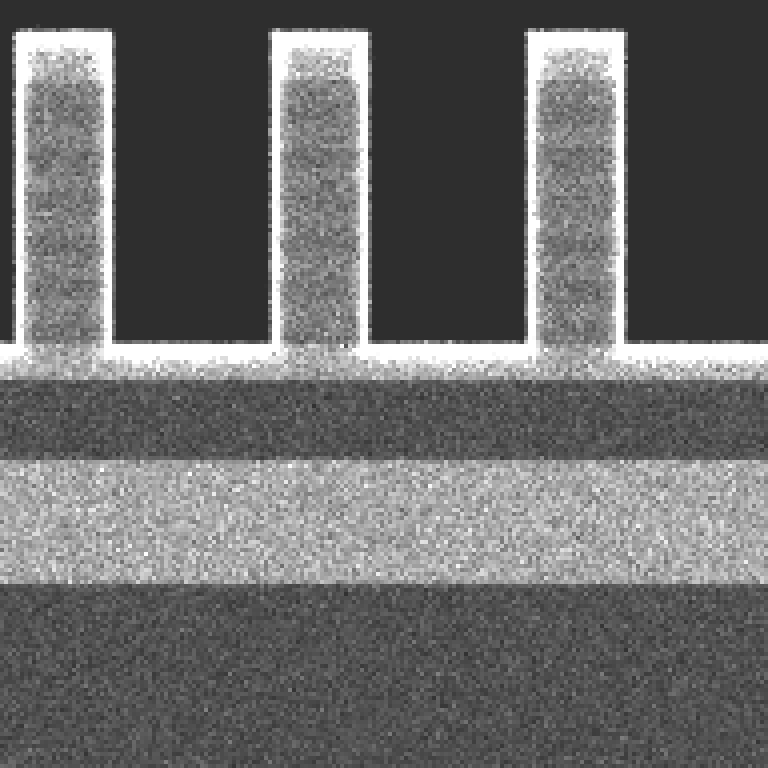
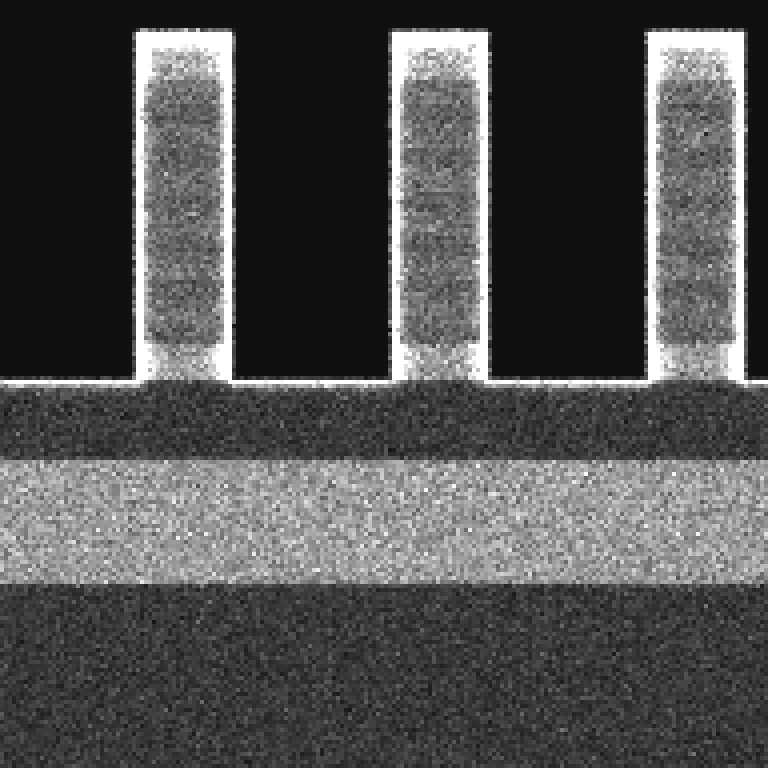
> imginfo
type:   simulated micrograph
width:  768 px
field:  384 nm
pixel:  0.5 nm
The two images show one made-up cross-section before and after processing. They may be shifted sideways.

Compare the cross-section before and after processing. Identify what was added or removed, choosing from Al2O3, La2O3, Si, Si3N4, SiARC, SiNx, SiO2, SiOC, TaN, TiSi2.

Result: SiO2 removed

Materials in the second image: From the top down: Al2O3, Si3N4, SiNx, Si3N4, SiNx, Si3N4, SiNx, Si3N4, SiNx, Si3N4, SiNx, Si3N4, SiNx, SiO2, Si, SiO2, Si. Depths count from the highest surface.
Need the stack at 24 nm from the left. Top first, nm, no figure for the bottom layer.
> empty 174, Si 40, SiO2 62, Si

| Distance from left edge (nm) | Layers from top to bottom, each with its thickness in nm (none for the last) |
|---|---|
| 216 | Al2O3 24, Si3N4 12, SiNx 10, Si3N4 12, SiNx 10, Si3N4 12, SiNx 10, Si3N4 12, SiNx 10, Si3N4 12, SiNx 10, Si3N4 12, SiNx 10, SiO2 18, Si 40, SiO2 62, Si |